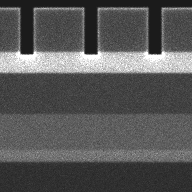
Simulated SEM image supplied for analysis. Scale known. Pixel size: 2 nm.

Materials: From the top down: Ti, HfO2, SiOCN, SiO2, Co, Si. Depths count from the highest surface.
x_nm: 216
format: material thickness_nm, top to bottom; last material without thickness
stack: Ti 88, HfO2 42, SiOCN 82, SiO2 72, Co 24, Si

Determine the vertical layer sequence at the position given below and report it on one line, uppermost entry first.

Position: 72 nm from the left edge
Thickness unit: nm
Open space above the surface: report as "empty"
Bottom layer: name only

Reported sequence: Ti 88, HfO2 42, SiOCN 82, SiO2 72, Co 24, Si